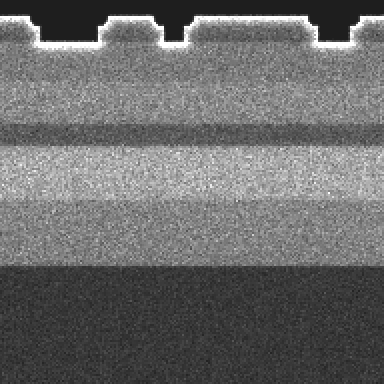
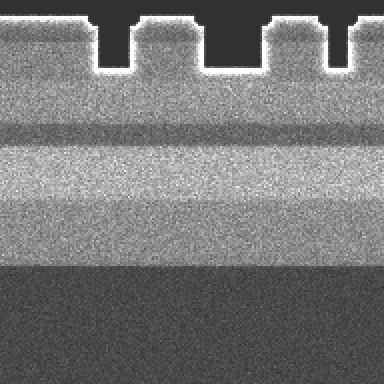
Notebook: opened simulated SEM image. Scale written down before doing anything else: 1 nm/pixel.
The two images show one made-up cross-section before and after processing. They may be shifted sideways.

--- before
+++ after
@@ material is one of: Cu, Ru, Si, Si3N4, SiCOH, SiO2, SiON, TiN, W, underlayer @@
SiO2 removed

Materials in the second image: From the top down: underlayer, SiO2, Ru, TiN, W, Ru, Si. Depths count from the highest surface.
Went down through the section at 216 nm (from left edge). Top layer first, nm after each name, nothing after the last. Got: empty 52, SiO2 14, Ru 42, TiN 22, W 54, Ru 66, Si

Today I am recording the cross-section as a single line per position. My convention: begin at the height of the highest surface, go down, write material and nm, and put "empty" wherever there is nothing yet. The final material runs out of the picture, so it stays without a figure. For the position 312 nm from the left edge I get underlayer 26, SiO2 40, Ru 42, TiN 22, W 54, Ru 66, Si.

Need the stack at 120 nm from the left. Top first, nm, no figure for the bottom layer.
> empty 52, SiO2 14, Ru 42, TiN 22, W 54, Ru 66, Si